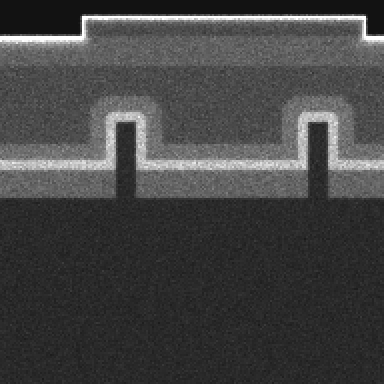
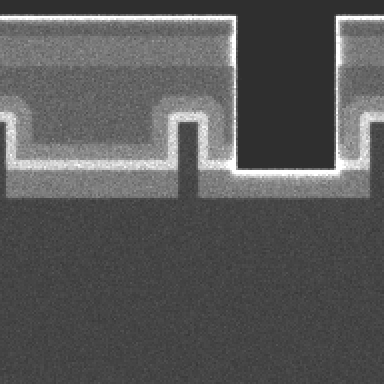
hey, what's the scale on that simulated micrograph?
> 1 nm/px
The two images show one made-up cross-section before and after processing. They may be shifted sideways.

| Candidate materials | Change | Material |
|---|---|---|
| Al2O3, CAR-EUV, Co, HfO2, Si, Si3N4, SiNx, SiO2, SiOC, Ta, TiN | removed | Co and HfO2 and SiO2 and TiN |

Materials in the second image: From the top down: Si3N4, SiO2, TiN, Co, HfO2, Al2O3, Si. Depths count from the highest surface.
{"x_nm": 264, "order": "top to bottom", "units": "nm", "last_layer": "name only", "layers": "empty 154, Al2O3 28, Si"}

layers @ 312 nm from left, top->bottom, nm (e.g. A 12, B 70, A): empty 154, Al2O3 28, Si